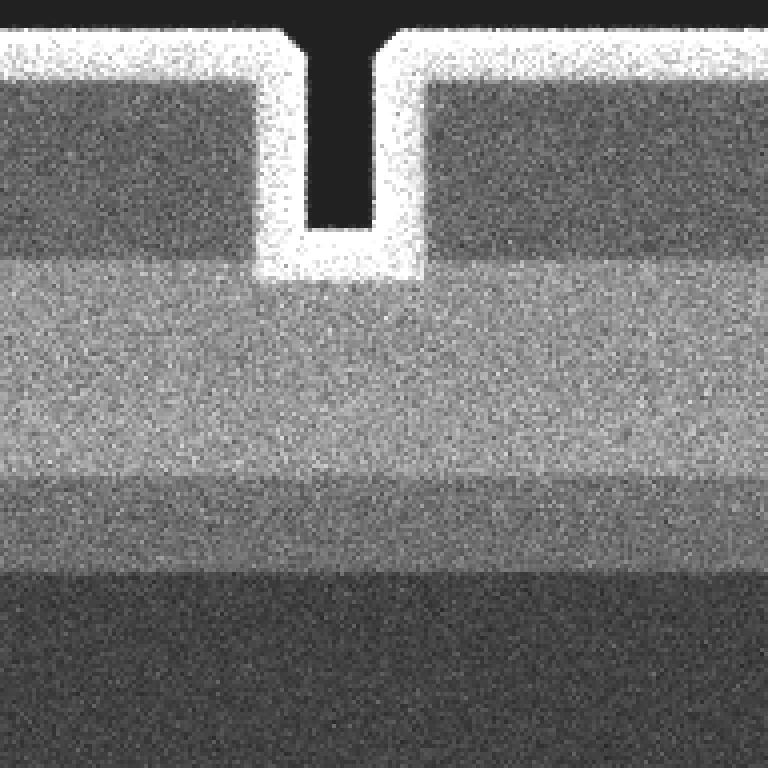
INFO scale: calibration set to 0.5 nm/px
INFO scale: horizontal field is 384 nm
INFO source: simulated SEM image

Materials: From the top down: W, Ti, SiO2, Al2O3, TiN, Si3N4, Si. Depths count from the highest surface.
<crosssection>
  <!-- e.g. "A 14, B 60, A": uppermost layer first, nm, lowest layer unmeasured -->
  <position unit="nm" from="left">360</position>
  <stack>W 24, Ti 90, SiO2 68, Al2O3 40, TiN 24, Si3N4 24, Si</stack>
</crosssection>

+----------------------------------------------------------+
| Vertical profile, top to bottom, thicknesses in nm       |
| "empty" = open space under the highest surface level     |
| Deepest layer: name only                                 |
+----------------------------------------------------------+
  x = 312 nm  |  W 24, Ti 90, SiO2 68, Al2O3 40, TiN 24, Si3N4 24, Si